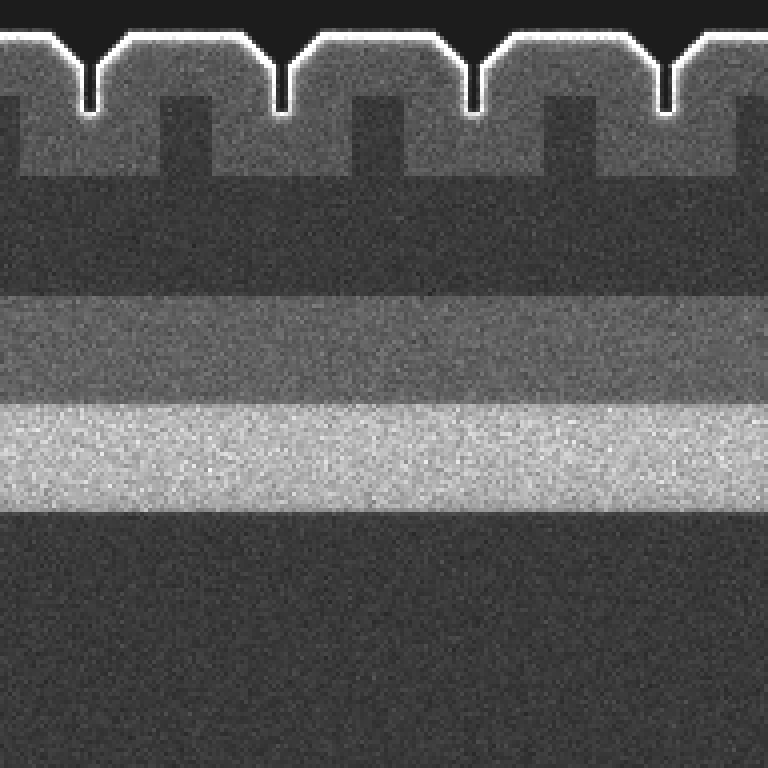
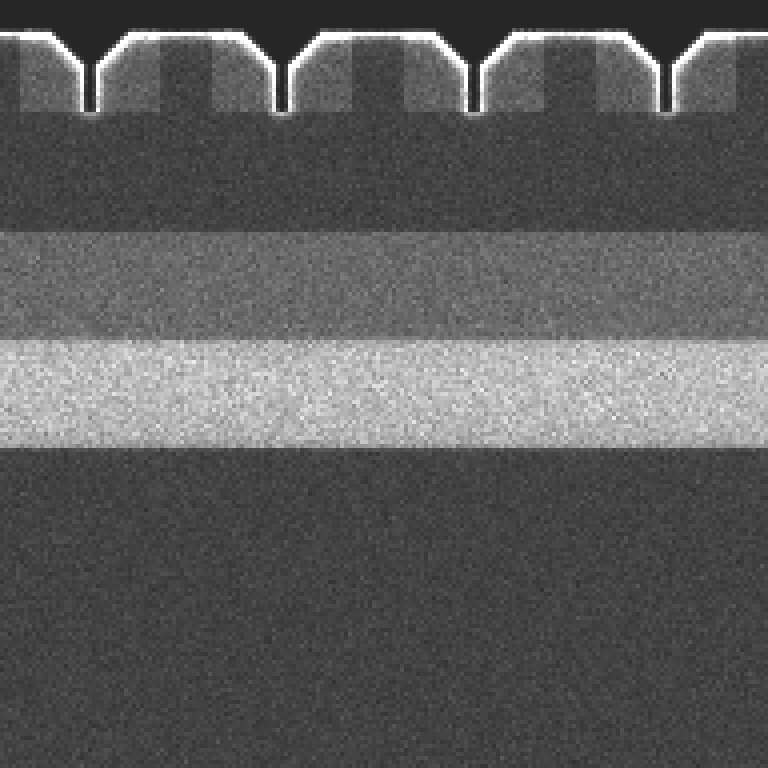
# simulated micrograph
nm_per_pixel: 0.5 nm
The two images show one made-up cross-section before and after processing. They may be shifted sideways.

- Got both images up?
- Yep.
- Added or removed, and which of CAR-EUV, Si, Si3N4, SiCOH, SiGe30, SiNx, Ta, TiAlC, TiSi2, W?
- removed, SiNx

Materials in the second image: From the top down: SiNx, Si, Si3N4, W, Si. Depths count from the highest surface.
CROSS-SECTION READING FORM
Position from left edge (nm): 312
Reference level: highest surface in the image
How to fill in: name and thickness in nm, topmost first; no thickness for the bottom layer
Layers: SiNx 40, Si 60, Si3N4 54, W 54, Si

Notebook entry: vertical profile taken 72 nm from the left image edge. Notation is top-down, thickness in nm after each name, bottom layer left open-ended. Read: SiNx 40, Si 60, Si3N4 54, W 54, Si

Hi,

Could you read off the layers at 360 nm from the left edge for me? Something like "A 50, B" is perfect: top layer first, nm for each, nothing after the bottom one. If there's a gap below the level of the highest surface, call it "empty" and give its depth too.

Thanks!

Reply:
SiNx 40, Si 60, Si3N4 54, W 54, Si